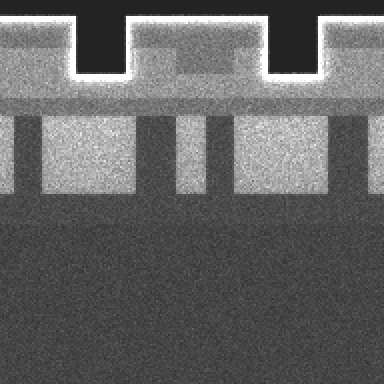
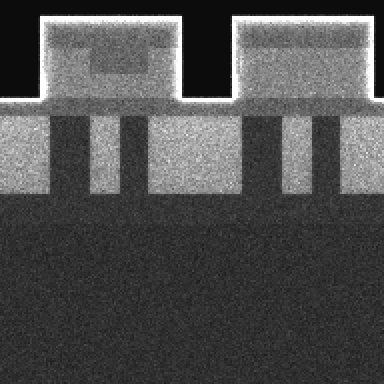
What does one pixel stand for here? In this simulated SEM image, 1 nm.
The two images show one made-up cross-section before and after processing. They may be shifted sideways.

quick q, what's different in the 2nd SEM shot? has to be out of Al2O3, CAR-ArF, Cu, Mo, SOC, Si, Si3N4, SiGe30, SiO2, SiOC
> SiO2 removed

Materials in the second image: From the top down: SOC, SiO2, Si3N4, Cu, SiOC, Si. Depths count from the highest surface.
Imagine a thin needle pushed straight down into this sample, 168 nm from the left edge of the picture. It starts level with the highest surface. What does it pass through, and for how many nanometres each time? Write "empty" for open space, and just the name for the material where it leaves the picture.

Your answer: SOC 32, SiO2 50, Si3N4 18, Cu 78, SiOC 30, Si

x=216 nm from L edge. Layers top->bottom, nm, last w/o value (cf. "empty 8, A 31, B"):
empty 82, Si3N4 18, Cu 78, SiOC 30, Si